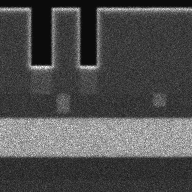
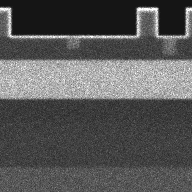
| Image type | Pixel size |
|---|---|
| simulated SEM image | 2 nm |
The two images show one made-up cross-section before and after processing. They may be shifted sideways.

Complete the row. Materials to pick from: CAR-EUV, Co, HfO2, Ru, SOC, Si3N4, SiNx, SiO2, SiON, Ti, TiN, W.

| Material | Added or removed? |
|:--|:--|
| SOC | removed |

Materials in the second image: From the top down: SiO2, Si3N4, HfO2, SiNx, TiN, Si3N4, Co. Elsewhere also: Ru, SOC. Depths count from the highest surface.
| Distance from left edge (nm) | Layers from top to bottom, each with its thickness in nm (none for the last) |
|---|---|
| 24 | empty 56, Si3N4 48, HfO2 78, SiNx 46, TiN 24, Si3N4 66, Co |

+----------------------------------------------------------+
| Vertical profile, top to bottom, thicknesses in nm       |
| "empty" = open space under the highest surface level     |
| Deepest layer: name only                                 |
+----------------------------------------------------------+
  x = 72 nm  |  empty 56, Si3N4 48, HfO2 78, SiNx 46, TiN 24, Si3N4 66, Co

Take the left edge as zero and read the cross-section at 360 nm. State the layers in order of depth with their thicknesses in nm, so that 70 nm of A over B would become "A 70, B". empty 56, Si3N4 48, HfO2 78, SiNx 46, TiN 24, Si3N4 66, Co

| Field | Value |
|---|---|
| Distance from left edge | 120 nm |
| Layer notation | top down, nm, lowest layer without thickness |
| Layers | empty 56, Si3N4 48, HfO2 78, SiNx 46, TiN 24, Si3N4 66, Co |